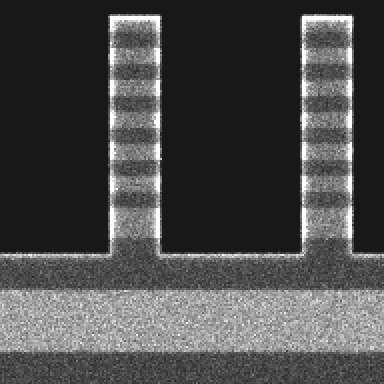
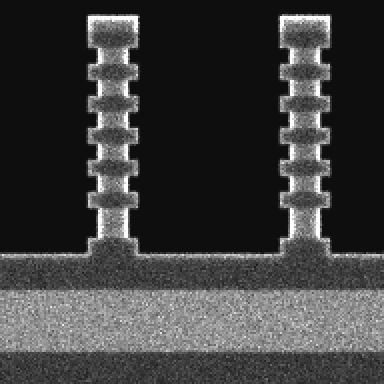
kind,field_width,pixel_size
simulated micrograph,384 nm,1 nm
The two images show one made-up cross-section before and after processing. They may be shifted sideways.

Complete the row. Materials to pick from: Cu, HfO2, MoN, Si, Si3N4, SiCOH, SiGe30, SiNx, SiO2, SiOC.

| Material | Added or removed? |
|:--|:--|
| Si3N4 | removed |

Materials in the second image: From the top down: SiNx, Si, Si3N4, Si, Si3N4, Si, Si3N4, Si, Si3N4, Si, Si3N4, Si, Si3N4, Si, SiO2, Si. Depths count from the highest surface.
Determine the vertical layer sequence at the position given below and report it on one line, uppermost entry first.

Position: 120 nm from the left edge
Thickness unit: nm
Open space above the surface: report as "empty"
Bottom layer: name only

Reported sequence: SiNx 16, Si 16, Si3N4 16, Si 16, Si3N4 16, Si 16, Si3N4 16, Si 16, Si3N4 16, Si 16, Si3N4 16, Si 16, Si3N4 30, Si 52, SiO2 62, Si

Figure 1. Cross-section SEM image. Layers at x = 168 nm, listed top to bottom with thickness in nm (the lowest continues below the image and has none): empty 238, Si 36, SiO2 62, Si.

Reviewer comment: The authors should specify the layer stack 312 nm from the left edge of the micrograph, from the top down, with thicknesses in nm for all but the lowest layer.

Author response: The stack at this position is SiNx 16, Si 16, Si3N4 16, Si 16, Si3N4 16, Si 16, Si3N4 16, Si 16, Si3N4 16, Si 16, Si3N4 16, Si 16, Si3N4 30, Si 52, SiO2 62, Si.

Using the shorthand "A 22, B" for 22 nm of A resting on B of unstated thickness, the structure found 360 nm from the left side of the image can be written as empty 238, Si 36, SiO2 62, Si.